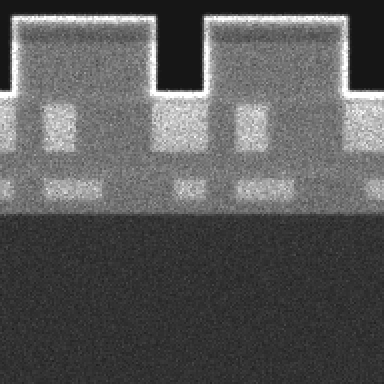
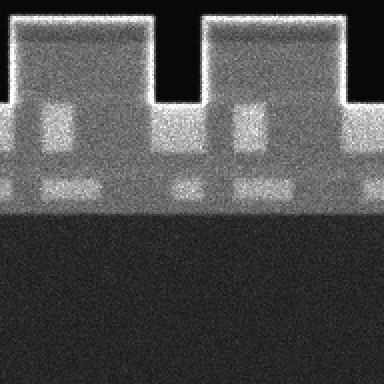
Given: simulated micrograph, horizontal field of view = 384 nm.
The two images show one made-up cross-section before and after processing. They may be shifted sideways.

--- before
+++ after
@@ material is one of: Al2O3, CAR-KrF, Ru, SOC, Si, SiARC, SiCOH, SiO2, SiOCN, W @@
Al2O3 removed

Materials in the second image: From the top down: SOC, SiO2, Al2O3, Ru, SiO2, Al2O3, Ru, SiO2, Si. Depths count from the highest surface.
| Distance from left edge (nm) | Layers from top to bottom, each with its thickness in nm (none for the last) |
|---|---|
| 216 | SOC 26, SiO2 50, Al2O3 12, SiO2 62, Al2O3 14, SiO2 34, Si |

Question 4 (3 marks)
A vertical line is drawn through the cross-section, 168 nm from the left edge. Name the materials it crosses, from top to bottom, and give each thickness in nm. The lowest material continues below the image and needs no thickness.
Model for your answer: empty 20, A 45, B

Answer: empty 88, Ru 48, SiO2 14, Al2O3 14, SiO2 34, Si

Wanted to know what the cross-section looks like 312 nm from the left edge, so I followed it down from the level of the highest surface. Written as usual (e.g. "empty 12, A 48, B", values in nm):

SOC 26, SiO2 50, Al2O3 12, SiO2 62, Al2O3 14, SiO2 34, Si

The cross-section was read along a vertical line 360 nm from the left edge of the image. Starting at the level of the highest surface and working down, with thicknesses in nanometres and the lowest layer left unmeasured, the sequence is empty 88, Ru 48, SiO2 14, Al2O3 14, SiO2 34, Si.